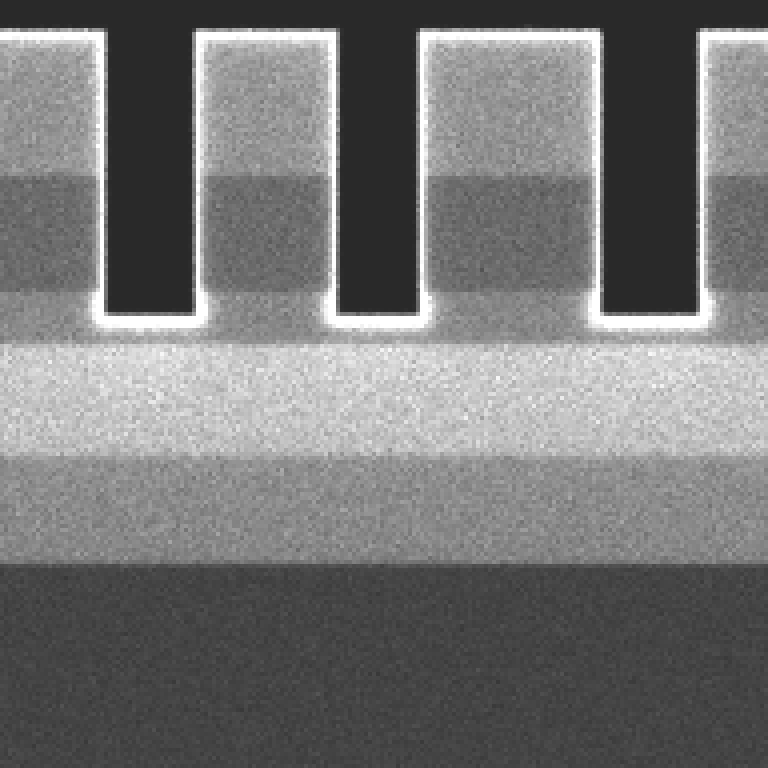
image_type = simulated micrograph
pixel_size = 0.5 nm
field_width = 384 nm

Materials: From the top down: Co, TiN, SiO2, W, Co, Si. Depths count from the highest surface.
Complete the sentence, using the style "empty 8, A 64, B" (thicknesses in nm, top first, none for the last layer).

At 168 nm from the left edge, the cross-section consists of empty 142, SiO2 14, W 56, Co 54, Si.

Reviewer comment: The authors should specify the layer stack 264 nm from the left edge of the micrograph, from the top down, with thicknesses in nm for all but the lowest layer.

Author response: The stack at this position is Co 72, TiN 58, SiO2 26, W 56, Co 54, Si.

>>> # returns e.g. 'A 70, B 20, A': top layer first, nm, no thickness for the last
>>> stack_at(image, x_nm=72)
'empty 142, SiO2 14, W 56, Co 54, Si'